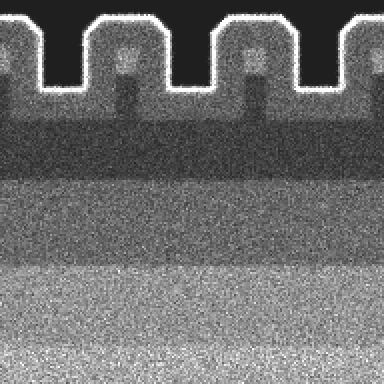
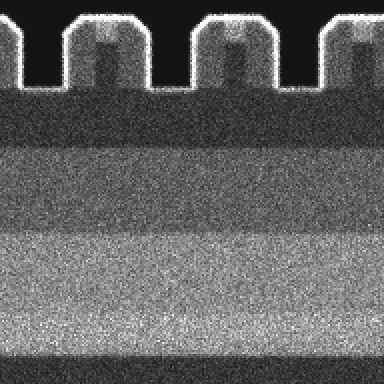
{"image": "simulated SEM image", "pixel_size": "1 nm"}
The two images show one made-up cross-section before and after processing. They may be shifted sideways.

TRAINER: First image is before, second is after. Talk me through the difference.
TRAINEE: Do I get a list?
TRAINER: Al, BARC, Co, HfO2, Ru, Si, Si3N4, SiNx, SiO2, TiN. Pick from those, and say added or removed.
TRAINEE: removed: SiNx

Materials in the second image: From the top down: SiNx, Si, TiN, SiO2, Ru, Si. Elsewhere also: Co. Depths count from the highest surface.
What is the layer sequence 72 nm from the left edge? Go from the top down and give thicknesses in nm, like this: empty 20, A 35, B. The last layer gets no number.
empty 8, SiNx 64, Si 60, TiN 86, SiO2 80, Ru 42, Si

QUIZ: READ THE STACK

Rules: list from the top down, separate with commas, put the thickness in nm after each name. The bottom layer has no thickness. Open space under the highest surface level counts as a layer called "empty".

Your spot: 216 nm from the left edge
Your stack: SiNx 72, Si 60, TiN 86, SiO2 80, Ru 42, Si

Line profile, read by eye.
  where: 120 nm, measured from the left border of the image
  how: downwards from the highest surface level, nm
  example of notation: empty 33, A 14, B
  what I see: SiNx 72, Si 60, TiN 86, SiO2 80, Ru 42, Si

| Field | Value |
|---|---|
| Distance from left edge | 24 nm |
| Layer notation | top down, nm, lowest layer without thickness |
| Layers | empty 72, Si 60, TiN 86, SiO2 80, Ru 42, Si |